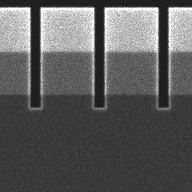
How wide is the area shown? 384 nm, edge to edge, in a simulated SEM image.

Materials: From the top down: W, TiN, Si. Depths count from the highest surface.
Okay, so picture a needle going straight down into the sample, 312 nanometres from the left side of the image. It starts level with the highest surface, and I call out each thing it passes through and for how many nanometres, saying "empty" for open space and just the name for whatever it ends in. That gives W 88, TiN 86, Si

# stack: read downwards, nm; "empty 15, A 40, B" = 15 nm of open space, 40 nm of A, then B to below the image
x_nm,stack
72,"empty 200, Si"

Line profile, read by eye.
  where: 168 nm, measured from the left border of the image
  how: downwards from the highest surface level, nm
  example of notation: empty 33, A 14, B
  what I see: W 88, TiN 86, Si